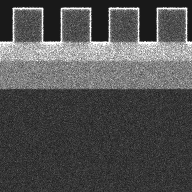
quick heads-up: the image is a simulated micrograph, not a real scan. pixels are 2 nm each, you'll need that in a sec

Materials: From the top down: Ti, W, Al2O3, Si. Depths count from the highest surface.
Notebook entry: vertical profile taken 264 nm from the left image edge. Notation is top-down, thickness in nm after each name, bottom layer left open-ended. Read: Ti 68, W 38, Al2O3 56, Si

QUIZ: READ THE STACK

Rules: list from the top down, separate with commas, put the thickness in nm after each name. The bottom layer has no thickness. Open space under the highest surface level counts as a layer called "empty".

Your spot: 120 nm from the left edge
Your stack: empty 68, W 38, Al2O3 56, Si